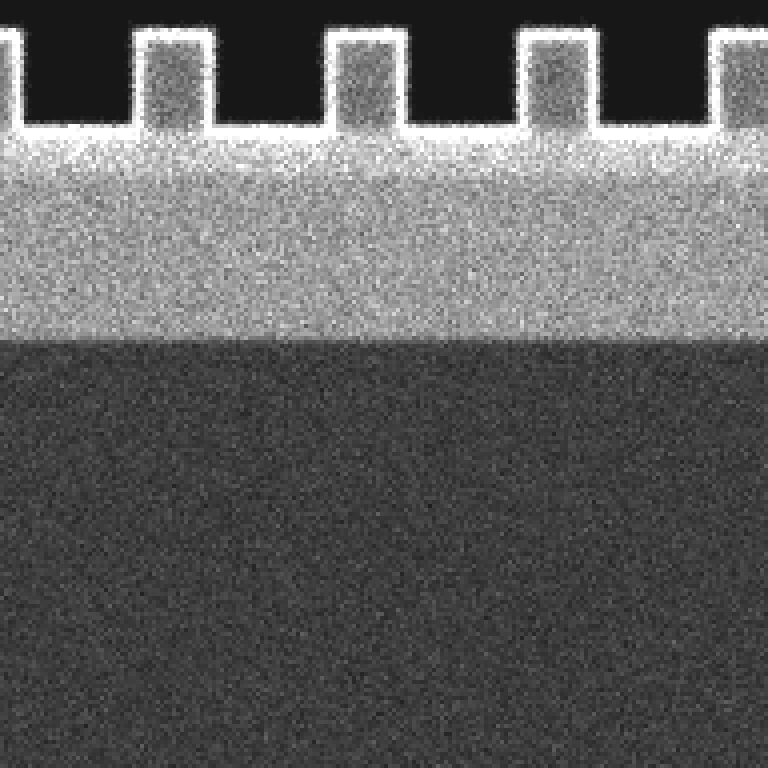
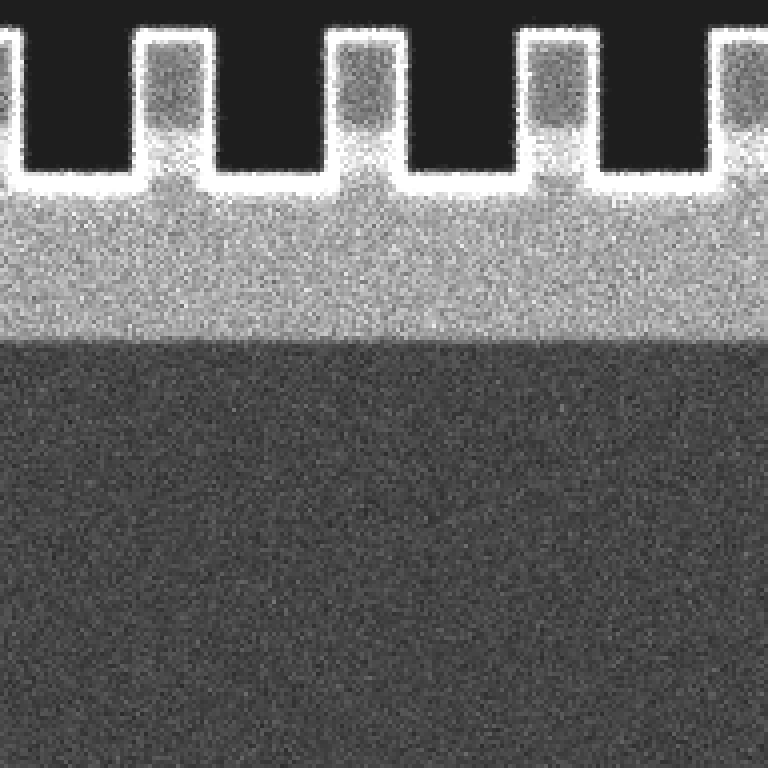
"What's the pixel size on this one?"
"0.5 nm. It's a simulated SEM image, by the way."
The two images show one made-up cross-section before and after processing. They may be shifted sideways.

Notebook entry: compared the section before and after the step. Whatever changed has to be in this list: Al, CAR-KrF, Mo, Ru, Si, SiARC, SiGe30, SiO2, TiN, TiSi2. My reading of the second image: Ru removed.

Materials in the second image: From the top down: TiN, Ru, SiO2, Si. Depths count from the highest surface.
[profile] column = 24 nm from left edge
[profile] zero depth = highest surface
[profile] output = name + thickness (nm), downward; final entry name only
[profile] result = empty 72, SiO2 82, Si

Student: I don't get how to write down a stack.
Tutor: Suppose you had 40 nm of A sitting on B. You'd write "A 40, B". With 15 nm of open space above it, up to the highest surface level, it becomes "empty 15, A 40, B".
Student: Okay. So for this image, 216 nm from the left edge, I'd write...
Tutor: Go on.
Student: empty 72, SiO2 82, Si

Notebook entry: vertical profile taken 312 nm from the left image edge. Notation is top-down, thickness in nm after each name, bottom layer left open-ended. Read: empty 72, SiO2 82, Si